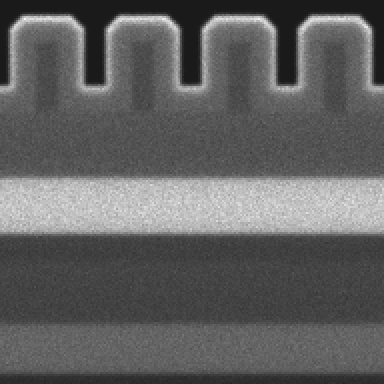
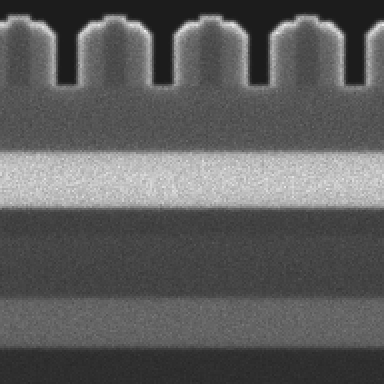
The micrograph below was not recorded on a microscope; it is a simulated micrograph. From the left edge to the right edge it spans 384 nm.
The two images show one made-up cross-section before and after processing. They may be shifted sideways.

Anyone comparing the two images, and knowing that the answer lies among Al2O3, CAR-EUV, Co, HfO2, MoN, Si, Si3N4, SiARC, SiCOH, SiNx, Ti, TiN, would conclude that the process removed Al2O3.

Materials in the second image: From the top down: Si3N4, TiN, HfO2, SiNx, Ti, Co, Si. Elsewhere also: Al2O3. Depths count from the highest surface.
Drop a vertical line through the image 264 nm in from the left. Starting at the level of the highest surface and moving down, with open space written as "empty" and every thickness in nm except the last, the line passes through empty 70, TiN 66, HfO2 56, SiNx 28, Ti 62, Co 50, Si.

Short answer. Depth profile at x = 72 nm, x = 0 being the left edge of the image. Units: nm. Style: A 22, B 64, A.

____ empty 70, TiN 66, HfO2 56, SiNx 28, Ti 62, Co 50, Si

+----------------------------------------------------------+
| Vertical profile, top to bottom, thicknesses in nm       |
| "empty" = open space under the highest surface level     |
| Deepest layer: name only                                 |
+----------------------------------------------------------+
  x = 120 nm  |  Si3N4 70, TiN 66, HfO2 56, SiNx 28, Ti 62, Co 50, Si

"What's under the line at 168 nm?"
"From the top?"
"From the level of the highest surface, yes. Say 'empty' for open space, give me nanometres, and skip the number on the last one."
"empty 70, TiN 66, HfO2 56, SiNx 28, Ti 62, Co 50, Si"